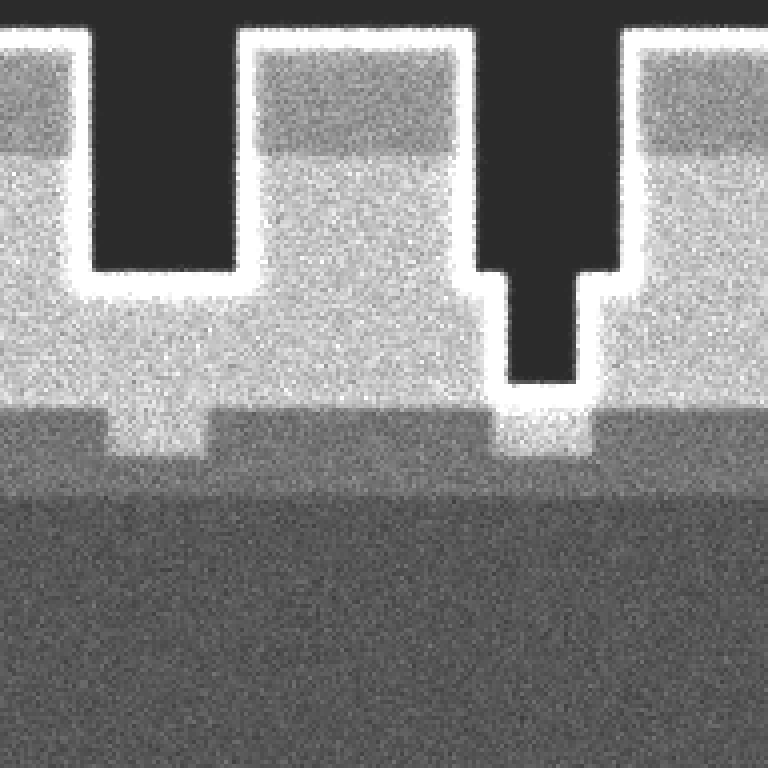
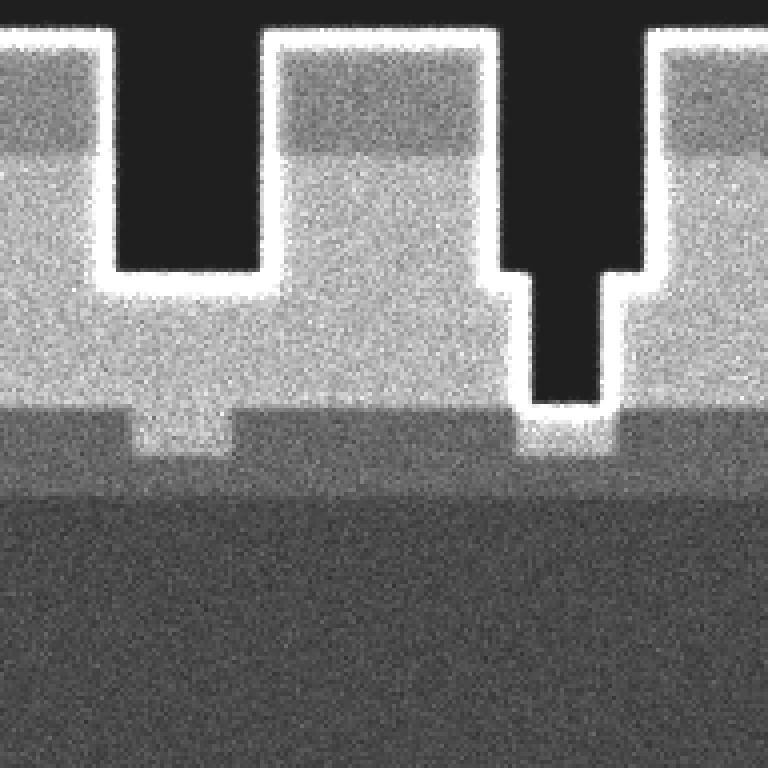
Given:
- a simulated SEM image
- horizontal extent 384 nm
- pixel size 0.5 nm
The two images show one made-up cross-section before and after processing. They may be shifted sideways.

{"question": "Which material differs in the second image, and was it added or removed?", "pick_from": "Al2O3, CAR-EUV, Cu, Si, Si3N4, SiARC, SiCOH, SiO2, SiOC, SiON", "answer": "Al2O3, removed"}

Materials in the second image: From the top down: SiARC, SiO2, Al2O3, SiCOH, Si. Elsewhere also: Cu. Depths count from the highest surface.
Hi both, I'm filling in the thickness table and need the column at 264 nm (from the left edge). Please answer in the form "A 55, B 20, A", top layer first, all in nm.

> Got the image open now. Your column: empty 188, Cu 24, SiCOH 20, Si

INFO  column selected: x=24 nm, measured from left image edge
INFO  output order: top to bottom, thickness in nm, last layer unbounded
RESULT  SiARC 62, SiO2 116, Al2O3 10, SiCOH 44, Si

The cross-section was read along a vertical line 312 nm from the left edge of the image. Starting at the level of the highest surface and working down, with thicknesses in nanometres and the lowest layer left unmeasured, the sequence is empty 122, SiO2 56, Al2O3 10, SiCOH 44, Si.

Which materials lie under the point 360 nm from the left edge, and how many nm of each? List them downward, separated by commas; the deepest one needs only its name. SiARC 62, SiO2 116, Al2O3 10, SiCOH 44, Si